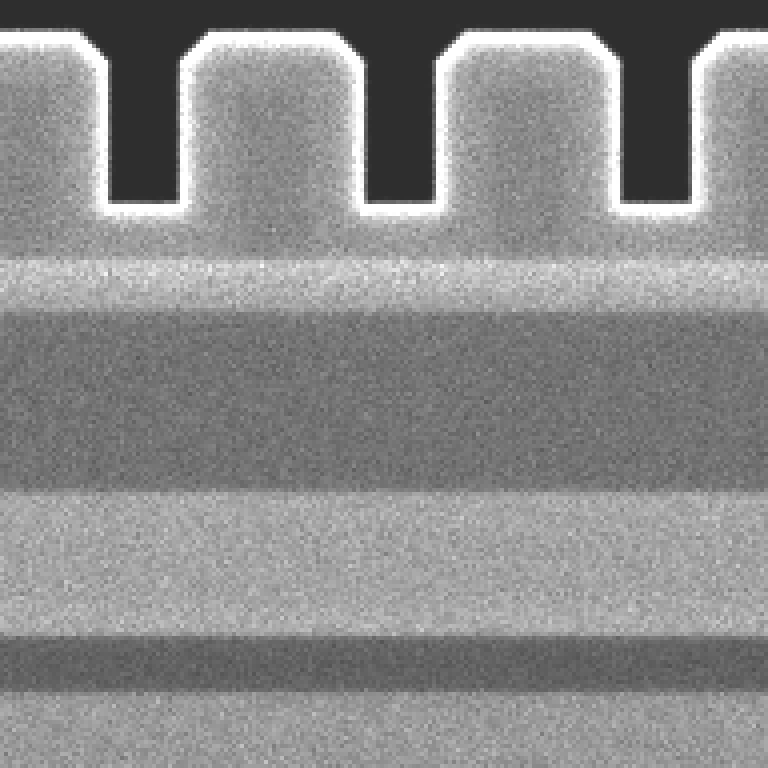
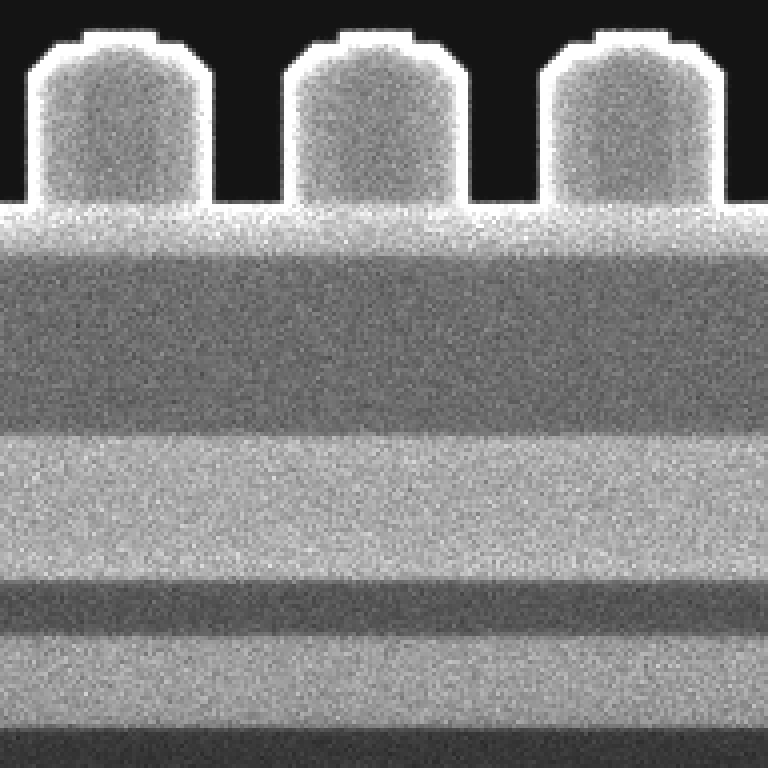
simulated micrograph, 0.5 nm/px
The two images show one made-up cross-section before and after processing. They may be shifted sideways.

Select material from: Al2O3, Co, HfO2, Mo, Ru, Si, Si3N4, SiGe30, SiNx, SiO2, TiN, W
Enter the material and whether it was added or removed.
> Al2O3 / removed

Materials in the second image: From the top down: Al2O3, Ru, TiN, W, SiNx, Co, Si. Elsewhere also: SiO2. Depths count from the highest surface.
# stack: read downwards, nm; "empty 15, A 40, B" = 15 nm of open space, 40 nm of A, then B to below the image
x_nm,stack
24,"empty 10, Al2O3 76, Ru 26, TiN 90, W 72, SiNx 28, Co 46, Si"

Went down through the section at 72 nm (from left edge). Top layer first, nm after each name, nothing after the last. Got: SiO2 86, Ru 26, TiN 90, W 72, SiNx 28, Co 46, Si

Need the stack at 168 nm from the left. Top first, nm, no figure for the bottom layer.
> empty 6, Al2O3 80, Ru 26, TiN 90, W 72, SiNx 28, Co 46, Si